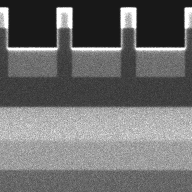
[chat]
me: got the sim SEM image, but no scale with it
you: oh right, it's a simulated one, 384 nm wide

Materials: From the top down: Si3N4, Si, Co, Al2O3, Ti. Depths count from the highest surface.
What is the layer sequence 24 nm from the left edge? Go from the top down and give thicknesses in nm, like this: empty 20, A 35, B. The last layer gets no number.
empty 80, Si3N4 58, Si 60, Co 68, Al2O3 58, Ti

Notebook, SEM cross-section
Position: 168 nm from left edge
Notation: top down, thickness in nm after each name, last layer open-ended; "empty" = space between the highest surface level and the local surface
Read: empty 80, Si3N4 58, Si 60, Co 68, Al2O3 58, Ti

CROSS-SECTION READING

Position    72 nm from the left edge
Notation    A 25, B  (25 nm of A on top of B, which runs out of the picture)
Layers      empty 80, Si3N4 58, Si 60, Co 68, Al2O3 58, Ti